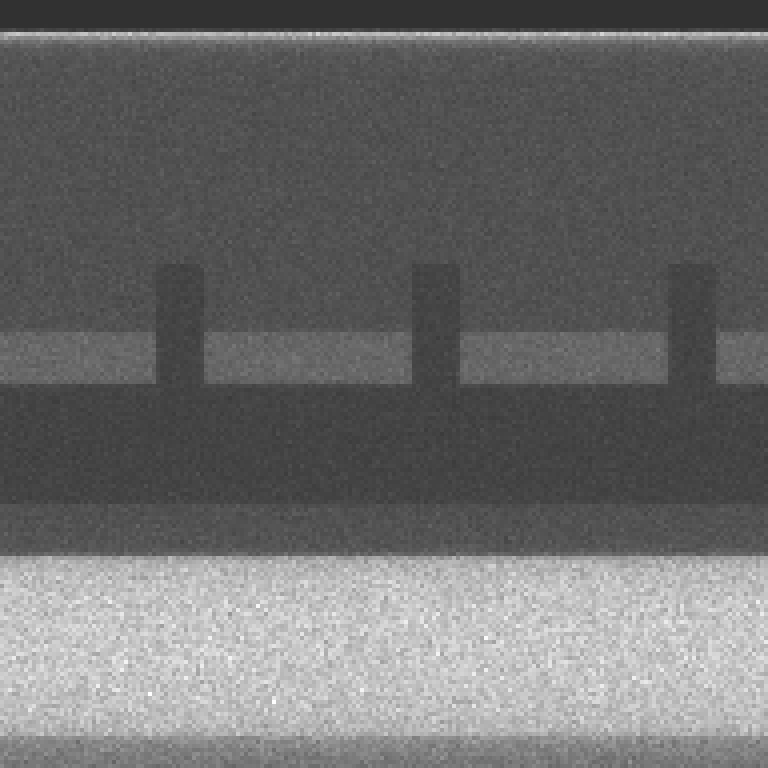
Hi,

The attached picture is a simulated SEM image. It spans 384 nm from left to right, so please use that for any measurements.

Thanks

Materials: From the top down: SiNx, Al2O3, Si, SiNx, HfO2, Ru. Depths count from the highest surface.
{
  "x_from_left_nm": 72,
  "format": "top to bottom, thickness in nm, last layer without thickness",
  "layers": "SiNx 150, Al2O3 26, Si 60, SiNx 26, HfO2 90, Ru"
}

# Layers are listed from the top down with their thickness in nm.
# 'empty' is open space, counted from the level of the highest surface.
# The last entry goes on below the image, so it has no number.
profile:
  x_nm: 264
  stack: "SiNx 150, Al2O3 26, Si 60, SiNx 26, HfO2 90, Ru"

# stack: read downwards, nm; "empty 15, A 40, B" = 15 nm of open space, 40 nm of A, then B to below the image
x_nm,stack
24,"SiNx 150, Al2O3 26, Si 60, SiNx 26, HfO2 90, Ru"